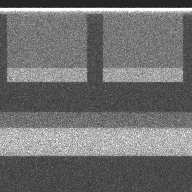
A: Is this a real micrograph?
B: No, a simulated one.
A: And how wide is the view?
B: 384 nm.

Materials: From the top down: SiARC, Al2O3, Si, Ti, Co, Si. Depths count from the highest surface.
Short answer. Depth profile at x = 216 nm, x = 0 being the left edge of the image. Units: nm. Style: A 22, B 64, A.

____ SiARC 120, Al2O3 28, Si 60, Ti 32, Co 56, Si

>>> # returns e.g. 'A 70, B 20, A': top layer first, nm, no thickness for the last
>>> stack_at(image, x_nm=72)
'SiARC 120, Al2O3 28, Si 60, Ti 32, Co 56, Si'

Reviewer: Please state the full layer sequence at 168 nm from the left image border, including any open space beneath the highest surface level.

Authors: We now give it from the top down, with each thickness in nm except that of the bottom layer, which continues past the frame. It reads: SiARC 120, Al2O3 28, Si 60, Ti 32, Co 56, Si